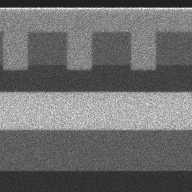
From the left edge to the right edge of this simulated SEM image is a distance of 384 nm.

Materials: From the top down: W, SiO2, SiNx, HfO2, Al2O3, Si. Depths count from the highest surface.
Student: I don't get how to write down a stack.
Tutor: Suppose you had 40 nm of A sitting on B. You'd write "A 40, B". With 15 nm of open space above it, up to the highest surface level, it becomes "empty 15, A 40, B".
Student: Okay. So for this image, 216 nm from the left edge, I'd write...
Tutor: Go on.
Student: W 48, SiO2 66, SiNx 54, HfO2 76, Al2O3 82, Si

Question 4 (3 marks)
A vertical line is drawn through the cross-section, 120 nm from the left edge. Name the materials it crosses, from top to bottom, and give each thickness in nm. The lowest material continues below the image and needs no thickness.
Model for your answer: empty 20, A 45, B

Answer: W 48, SiO2 66, SiNx 54, HfO2 76, Al2O3 82, Si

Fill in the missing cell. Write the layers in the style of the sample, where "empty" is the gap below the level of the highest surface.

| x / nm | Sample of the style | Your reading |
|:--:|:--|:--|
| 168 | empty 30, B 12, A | W 124, SiNx 44, HfO2 76, Al2O3 82, Si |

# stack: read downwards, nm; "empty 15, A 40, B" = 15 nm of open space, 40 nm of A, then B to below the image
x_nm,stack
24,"W 124, SiNx 44, HfO2 76, Al2O3 82, Si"